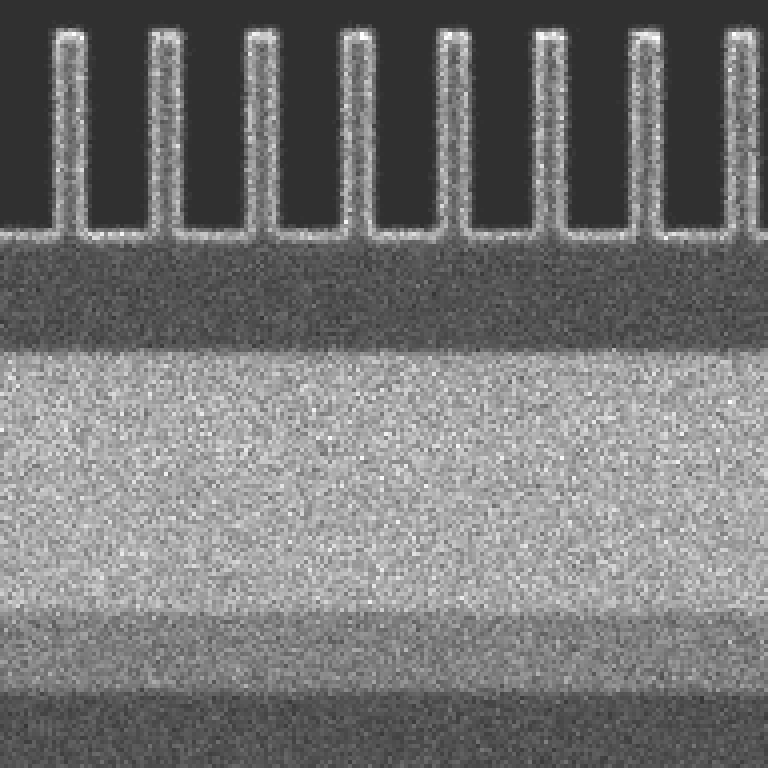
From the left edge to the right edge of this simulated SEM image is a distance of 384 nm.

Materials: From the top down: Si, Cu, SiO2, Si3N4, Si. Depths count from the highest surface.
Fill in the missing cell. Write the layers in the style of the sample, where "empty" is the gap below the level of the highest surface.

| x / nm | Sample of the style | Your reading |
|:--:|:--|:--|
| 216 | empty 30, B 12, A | empty 100, Si 60, Cu 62, SiO2 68, Si3N4 40, Si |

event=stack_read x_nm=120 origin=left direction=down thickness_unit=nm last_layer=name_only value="empty 100, Si 60, Cu 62, SiO2 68, Si3N4 40, Si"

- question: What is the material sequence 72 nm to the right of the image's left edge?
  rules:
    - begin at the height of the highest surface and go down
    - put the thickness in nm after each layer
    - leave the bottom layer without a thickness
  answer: empty 100, Si 60, Cu 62, SiO2 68, Si3N4 40, Si